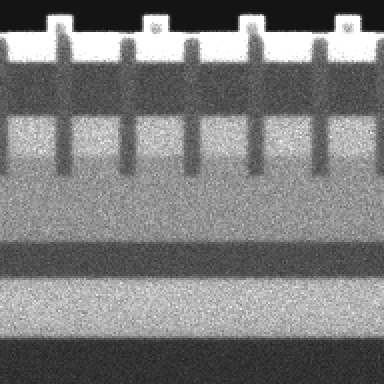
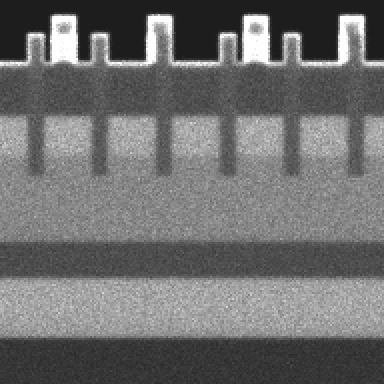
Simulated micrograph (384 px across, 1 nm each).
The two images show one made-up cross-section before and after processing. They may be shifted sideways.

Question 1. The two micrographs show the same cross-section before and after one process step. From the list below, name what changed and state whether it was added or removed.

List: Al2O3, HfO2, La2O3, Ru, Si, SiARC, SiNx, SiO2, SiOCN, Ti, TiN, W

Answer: HfO2, removed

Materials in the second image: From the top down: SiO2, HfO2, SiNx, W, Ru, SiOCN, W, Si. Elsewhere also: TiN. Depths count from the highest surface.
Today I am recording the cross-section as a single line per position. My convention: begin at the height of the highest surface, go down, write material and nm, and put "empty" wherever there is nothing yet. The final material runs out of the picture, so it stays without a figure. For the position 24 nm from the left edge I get empty 46, SiNx 54, W 40, Ru 86, SiOCN 36, W 60, Si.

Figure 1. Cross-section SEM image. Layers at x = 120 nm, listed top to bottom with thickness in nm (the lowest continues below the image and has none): empty 46, SiNx 54, W 40, Ru 86, SiOCN 36, W 60, Si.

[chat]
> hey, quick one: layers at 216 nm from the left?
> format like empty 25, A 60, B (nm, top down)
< empty 46, SiNx 54, W 40, Ru 86, SiOCN 36, W 60, Si